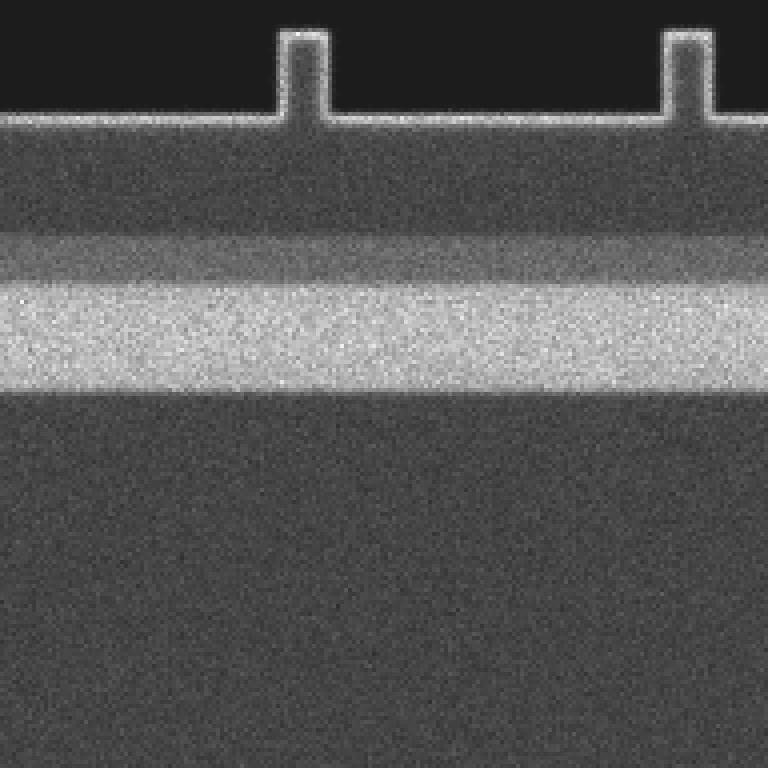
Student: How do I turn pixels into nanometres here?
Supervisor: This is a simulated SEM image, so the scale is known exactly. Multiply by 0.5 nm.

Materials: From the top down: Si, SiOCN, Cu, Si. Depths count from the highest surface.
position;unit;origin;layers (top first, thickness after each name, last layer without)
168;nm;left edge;empty 42, Si 60, SiOCN 24, Cu 54, Si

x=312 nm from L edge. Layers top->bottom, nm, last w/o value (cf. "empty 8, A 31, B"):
empty 42, Si 60, SiOCN 24, Cu 54, Si